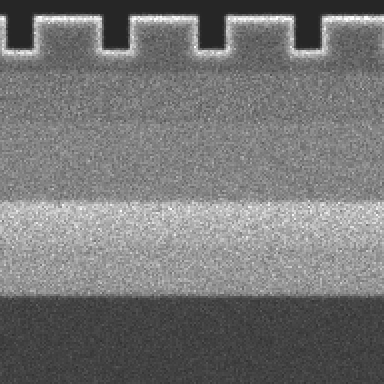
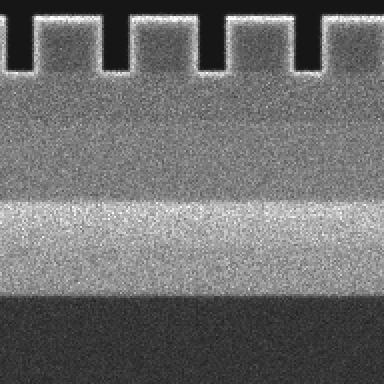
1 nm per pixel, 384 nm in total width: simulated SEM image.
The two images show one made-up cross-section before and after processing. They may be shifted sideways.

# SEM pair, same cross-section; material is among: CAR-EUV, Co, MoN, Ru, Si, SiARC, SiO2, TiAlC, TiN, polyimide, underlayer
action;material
removed;underlayer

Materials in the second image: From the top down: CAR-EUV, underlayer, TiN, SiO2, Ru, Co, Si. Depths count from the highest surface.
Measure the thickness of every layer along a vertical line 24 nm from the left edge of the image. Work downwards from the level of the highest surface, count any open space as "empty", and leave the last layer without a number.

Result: empty 56, TiN 50, SiO2 80, Ru 44, Co 50, Si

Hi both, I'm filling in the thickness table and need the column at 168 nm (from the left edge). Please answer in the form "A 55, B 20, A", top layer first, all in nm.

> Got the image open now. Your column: CAR-EUV 34, underlayer 22, TiN 50, SiO2 80, Ru 44, Co 50, Si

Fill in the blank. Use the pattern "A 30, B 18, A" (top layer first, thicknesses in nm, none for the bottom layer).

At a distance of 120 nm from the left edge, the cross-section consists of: empty 56, TiN 50, SiO2 80, Ru 44, Co 50, Si